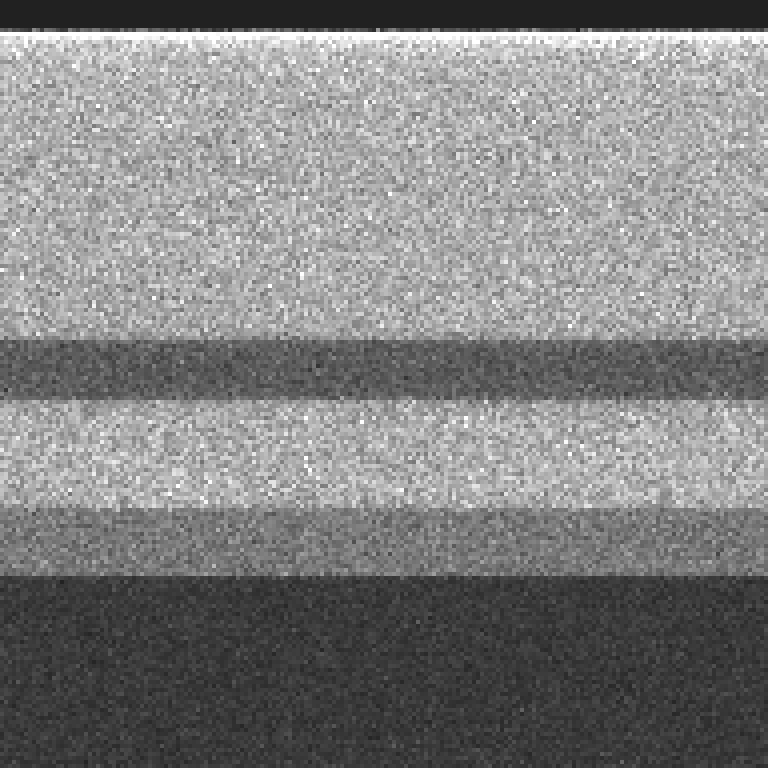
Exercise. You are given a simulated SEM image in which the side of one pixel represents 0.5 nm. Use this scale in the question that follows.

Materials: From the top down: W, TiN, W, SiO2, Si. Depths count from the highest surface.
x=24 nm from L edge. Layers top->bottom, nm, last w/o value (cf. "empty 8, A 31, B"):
W 154, TiN 30, W 54, SiO2 34, Si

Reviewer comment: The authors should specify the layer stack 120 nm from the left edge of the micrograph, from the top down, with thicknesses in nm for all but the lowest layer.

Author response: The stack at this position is W 154, TiN 30, W 54, SiO2 34, Si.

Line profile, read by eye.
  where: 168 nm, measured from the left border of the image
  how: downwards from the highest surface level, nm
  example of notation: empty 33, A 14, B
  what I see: W 154, TiN 30, W 54, SiO2 34, Si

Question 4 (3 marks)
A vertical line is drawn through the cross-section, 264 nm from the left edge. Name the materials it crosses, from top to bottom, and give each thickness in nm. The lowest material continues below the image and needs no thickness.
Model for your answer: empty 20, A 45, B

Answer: W 154, TiN 30, W 54, SiO2 34, Si